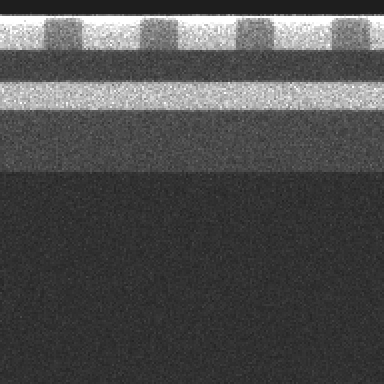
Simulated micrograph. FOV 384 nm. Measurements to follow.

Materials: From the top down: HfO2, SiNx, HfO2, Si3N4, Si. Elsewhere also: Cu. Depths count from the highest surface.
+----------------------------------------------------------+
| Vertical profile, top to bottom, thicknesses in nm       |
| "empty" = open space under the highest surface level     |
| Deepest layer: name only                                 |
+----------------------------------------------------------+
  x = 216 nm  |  HfO2 34, SiNx 32, HfO2 28, Si3N4 62, Si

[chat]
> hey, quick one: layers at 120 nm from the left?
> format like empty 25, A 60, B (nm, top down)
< HfO2 34, SiNx 32, HfO2 28, Si3N4 62, Si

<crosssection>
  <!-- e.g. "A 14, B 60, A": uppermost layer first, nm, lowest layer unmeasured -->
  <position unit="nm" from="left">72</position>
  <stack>Cu 34, SiNx 32, HfO2 28, Si3N4 62, Si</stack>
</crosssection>